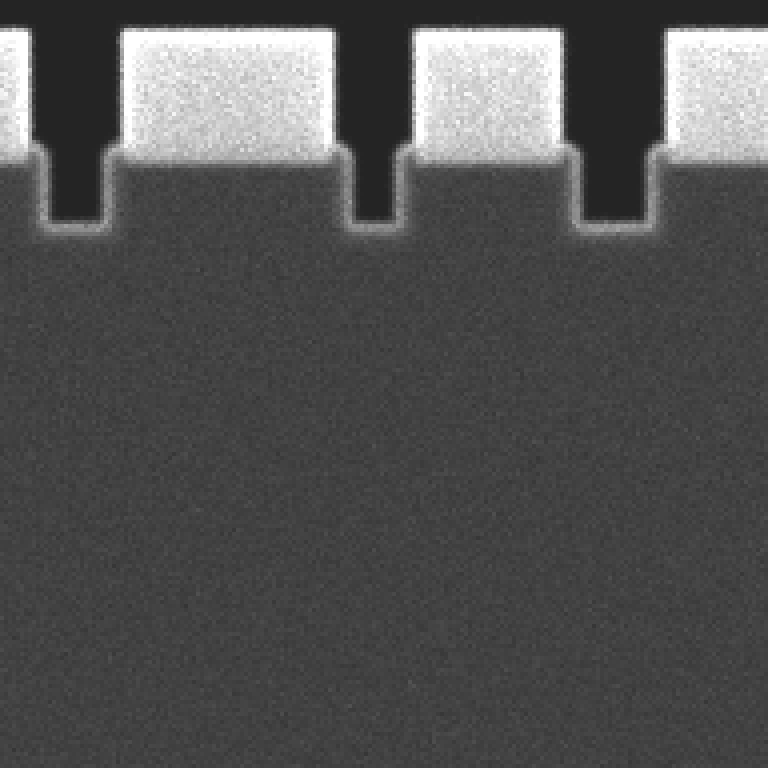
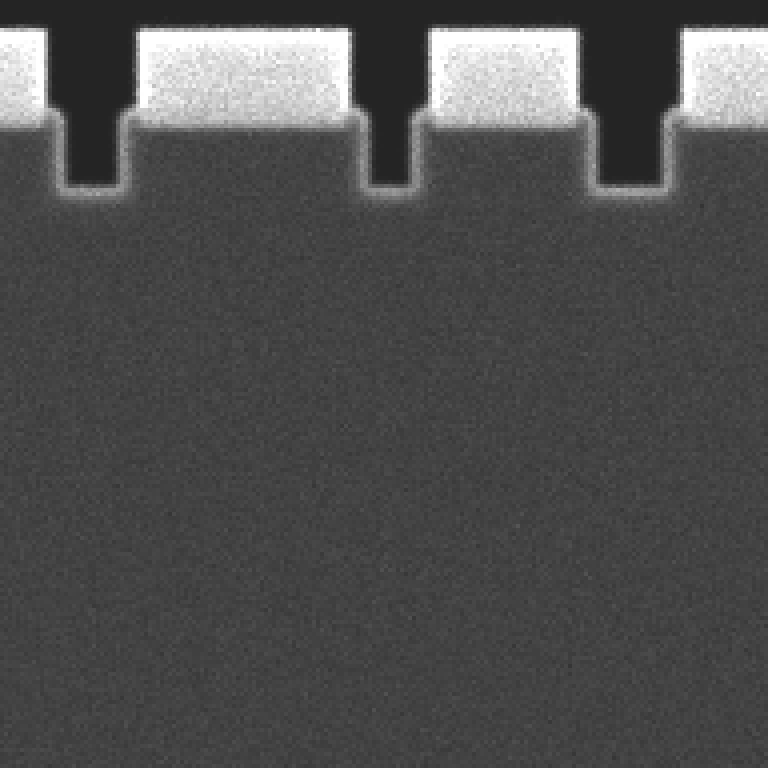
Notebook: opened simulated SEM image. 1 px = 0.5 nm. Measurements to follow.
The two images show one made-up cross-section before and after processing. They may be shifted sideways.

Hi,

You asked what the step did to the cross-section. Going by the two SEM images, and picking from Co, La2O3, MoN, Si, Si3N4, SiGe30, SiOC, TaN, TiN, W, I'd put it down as W, removed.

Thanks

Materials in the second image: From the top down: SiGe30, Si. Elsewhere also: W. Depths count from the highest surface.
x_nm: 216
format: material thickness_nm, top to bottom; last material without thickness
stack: W 48, Si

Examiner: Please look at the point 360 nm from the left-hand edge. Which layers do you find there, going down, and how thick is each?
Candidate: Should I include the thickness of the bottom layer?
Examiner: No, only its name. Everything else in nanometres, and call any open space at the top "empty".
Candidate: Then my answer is W 48, Si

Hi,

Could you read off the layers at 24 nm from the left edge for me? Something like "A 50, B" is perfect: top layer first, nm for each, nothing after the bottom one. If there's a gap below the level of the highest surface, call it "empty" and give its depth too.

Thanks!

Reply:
empty 38, SiGe30 50, Si